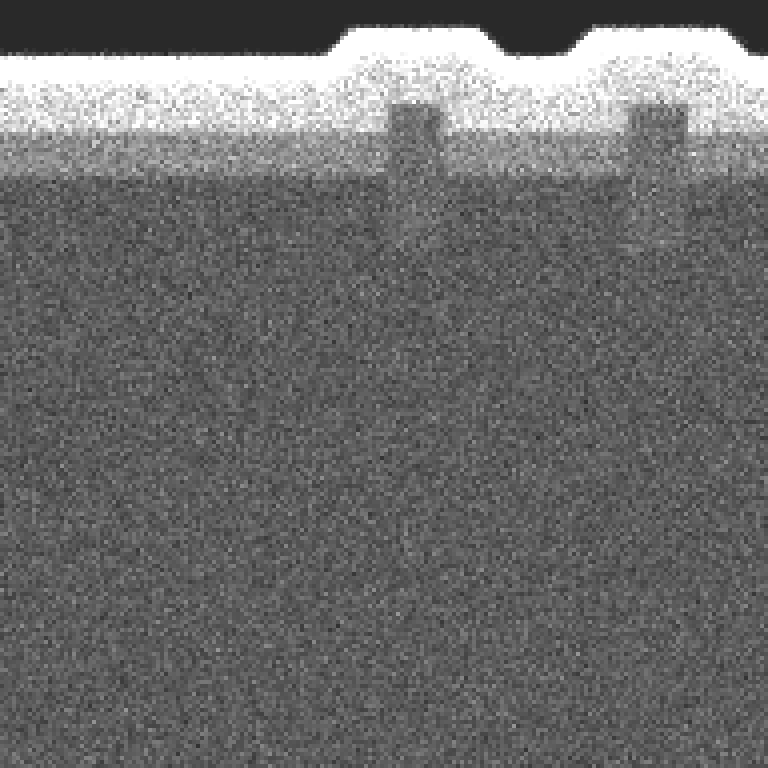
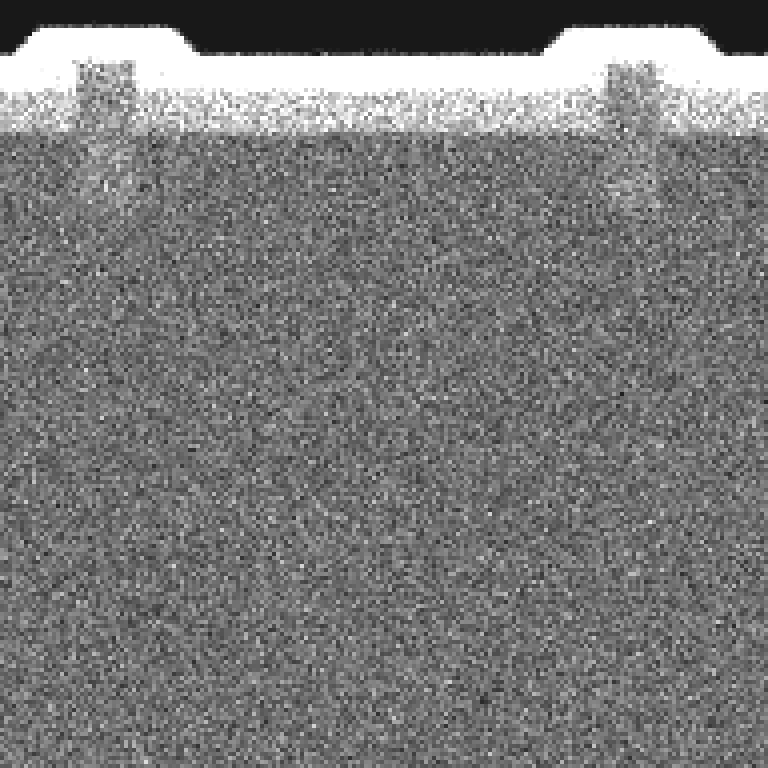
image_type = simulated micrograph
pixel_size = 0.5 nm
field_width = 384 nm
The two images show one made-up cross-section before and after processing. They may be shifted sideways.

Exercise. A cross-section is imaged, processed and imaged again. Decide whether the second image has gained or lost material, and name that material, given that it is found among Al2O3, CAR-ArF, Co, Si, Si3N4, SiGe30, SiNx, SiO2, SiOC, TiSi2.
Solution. removed: SiO2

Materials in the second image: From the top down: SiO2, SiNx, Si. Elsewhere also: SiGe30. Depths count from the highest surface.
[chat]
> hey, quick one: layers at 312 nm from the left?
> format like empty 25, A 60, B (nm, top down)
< SiO2 14, SiGe30 76, Si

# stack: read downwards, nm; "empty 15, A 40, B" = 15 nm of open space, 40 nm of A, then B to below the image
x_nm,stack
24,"SiO2 28, SiNx 22, Si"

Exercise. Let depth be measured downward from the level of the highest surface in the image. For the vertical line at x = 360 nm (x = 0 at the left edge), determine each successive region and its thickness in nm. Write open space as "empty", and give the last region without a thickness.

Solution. empty 14, SiO2 14, SiNx 22, Si